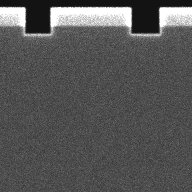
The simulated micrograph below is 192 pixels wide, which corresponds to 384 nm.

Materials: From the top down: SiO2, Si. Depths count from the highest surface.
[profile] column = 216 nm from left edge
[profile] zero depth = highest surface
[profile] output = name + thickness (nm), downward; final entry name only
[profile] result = SiO2 36, Si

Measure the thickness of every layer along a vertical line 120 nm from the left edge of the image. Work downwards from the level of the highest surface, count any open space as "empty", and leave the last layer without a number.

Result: SiO2 36, Si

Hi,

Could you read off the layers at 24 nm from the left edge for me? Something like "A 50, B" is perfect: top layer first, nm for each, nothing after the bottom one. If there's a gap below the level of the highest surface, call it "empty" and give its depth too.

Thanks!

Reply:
SiO2 36, Si